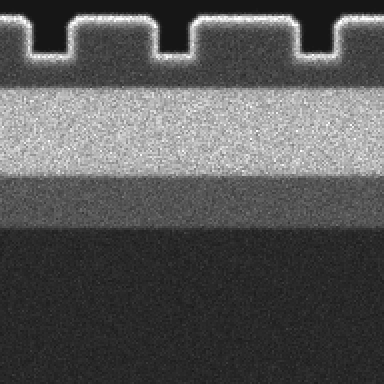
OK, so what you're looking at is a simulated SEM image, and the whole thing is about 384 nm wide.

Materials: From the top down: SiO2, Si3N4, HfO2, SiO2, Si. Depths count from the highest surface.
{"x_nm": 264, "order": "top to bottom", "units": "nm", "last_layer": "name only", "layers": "SiO2 12, Si3N4 60, HfO2 88, SiO2 52, Si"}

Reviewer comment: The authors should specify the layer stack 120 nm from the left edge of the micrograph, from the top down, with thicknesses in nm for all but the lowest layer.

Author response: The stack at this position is SiO2 12, Si3N4 60, HfO2 88, SiO2 52, Si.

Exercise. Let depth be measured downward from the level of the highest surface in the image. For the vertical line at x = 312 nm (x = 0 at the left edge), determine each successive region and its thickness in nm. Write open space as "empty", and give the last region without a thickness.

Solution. empty 38, SiO2 12, Si3N4 22, HfO2 88, SiO2 52, Si